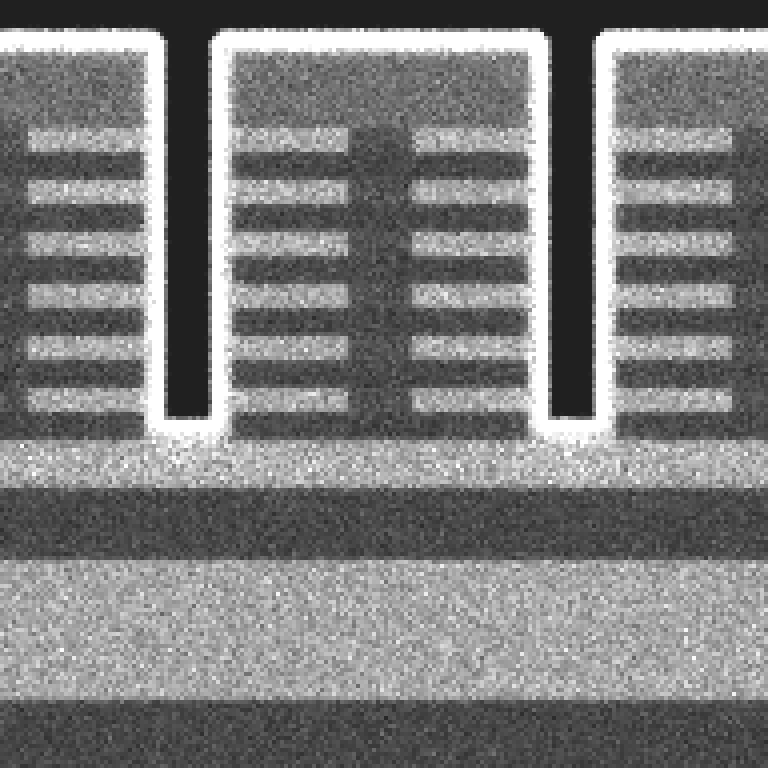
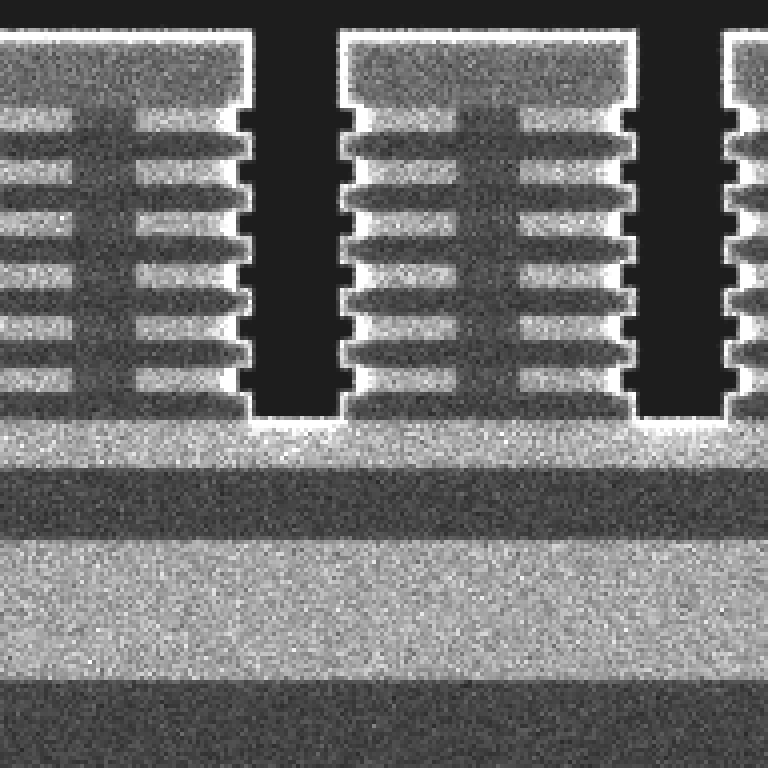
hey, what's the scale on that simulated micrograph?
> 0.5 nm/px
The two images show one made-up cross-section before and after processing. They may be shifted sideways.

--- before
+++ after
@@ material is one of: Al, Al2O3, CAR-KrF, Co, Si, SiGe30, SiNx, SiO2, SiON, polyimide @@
Al2O3 removed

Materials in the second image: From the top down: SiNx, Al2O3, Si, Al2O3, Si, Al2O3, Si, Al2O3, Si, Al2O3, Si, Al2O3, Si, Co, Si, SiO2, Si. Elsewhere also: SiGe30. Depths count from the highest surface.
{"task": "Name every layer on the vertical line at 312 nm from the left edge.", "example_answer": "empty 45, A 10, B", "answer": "SiNx 38, empty 12, Si 14, empty 12, Si 14, empty 12, Si 14, empty 12, Si 14, empty 12, Si 14, empty 12, Si 14, Co 24, Si 36, SiO2 70, Si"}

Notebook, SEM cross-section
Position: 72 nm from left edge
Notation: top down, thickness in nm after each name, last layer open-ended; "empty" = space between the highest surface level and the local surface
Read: SiNx 38, Al2O3 12, Si 14, Al2O3 12, Si 14, Al2O3 12, Si 14, Al2O3 12, Si 14, Al2O3 12, Si 14, Al2O3 12, Si 14, Co 24, Si 36, SiO2 70, Si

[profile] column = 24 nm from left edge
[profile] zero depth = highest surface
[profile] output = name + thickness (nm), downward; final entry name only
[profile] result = SiNx 38, Al2O3 12, Si 14, Al2O3 12, Si 14, Al2O3 12, Si 14, Al2O3 12, Si 14, Al2O3 12, Si 14, Al2O3 12, Si 14, Co 24, Si 36, SiO2 70, Si